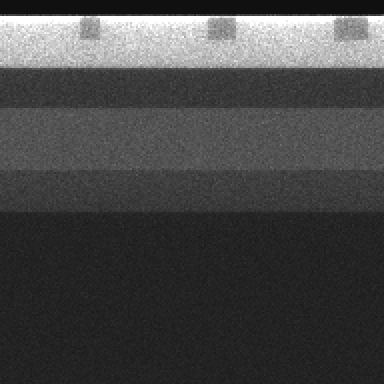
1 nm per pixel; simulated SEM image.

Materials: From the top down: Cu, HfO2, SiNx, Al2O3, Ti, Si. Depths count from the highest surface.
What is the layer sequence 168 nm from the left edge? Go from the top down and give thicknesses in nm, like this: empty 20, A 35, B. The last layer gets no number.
HfO2 52, SiNx 40, Al2O3 62, Ti 42, Si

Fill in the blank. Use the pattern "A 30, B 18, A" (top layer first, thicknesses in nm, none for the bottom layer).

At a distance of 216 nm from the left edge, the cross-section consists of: Cu 24, HfO2 28, SiNx 40, Al2O3 62, Ti 42, Si